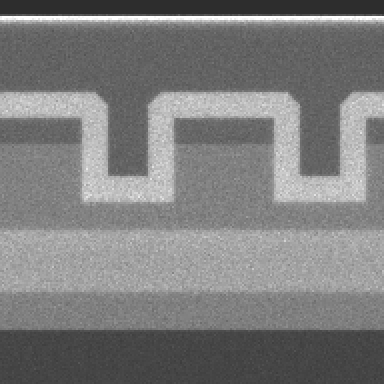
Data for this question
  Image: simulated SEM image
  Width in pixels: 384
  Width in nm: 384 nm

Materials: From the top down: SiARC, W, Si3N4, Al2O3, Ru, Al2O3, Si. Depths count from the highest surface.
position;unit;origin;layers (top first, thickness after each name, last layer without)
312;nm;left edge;SiARC 160, W 26, Al2O3 28, Ru 62, Al2O3 38, Si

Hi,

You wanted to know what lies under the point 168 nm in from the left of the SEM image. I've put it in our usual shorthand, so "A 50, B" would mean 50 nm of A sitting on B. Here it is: SiARC 76, W 110, Al2O3 28, Ru 62, Al2O3 38, Si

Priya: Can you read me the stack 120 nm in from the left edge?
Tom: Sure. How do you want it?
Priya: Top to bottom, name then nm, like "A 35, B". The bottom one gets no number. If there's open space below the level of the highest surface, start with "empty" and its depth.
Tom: SiARC 160, W 26, Al2O3 28, Ru 62, Al2O3 38, Si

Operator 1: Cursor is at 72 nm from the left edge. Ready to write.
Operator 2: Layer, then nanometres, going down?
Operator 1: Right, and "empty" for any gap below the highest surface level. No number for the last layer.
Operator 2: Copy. SiARC 76, W 26, Si3N4 26, Al2O3 86, Ru 62, Al2O3 38, Si